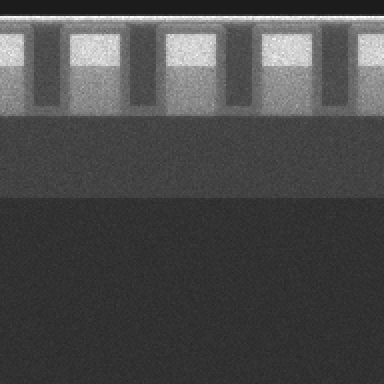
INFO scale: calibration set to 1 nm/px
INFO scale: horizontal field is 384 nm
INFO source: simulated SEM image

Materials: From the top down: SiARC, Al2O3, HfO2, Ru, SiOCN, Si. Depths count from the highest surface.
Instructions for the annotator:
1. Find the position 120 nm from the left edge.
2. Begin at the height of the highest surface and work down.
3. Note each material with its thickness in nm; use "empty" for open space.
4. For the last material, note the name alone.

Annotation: SiARC 8, Al2O3 92, SiOCN 82, Si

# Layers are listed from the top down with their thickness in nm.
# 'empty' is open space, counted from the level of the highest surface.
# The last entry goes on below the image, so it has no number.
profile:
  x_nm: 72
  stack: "SiARC 8, Al2O3 10, HfO2 32, Ru 50, SiOCN 82, Si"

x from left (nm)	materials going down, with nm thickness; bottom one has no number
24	SiARC 8, Al2O3 92, SiOCN 82, Si